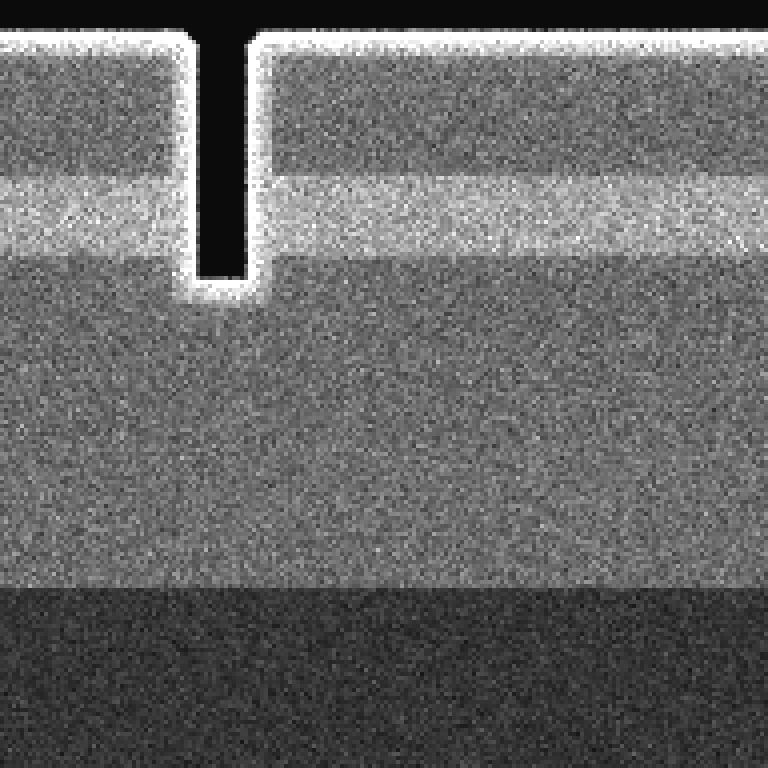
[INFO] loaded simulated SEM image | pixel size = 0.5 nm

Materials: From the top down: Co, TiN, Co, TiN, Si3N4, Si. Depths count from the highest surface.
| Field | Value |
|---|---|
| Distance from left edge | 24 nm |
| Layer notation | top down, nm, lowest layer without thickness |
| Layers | Co 12, TiN 60, Co 40, TiN 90, Si3N4 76, Si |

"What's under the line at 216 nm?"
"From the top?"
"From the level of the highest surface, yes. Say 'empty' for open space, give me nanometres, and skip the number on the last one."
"Co 12, TiN 60, Co 40, TiN 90, Si3N4 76, Si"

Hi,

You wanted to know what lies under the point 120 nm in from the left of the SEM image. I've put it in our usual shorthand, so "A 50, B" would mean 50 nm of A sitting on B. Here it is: empty 124, Co 12, TiN 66, Si3N4 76, Si